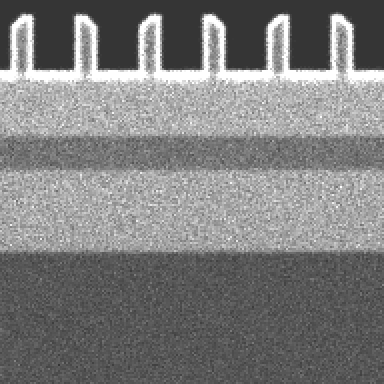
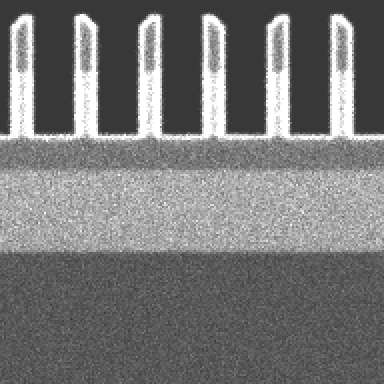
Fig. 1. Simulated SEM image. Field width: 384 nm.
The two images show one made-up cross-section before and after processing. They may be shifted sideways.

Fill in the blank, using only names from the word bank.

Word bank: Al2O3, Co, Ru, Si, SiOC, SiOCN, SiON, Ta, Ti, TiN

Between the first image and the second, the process removed Al2O3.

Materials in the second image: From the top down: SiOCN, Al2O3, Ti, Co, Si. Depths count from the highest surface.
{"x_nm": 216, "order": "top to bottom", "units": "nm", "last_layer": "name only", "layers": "empty 4, SiOCN 52, Al2O3 64, Ti 34, Co 82, Si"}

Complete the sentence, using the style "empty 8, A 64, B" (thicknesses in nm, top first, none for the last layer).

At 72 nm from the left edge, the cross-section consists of empty 120, Ti 34, Co 82, Si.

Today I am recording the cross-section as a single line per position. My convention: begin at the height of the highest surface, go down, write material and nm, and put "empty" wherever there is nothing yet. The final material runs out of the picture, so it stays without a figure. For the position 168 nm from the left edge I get empty 120, Ti 34, Co 82, Si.